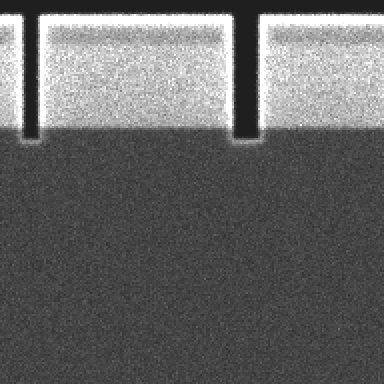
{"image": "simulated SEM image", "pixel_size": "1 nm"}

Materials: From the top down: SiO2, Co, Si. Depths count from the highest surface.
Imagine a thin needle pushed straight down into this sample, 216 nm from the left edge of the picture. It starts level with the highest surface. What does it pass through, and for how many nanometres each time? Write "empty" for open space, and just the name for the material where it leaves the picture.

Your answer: SiO2 28, Co 84, Si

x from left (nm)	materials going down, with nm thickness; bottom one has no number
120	SiO2 28, Co 84, Si